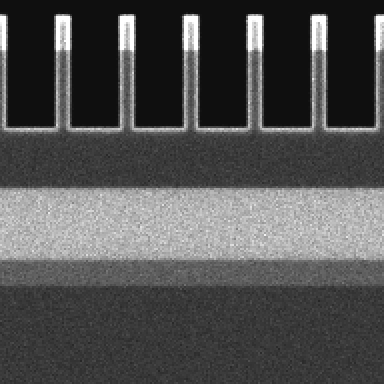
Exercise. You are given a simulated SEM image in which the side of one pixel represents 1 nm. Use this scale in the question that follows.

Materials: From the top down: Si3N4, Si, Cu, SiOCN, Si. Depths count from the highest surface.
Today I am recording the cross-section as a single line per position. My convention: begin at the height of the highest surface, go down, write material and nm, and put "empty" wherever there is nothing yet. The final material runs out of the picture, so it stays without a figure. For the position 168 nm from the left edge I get empty 112, Si 60, Cu 72, SiOCN 26, Si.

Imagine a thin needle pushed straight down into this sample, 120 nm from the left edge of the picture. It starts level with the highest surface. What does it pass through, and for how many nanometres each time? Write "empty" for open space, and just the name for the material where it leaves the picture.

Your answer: Si3N4 34, Si 138, Cu 72, SiOCN 26, Si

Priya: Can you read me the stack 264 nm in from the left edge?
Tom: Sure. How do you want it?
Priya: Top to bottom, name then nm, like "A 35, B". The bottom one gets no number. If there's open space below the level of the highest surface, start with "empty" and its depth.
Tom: empty 112, Si 60, Cu 72, SiOCN 26, Si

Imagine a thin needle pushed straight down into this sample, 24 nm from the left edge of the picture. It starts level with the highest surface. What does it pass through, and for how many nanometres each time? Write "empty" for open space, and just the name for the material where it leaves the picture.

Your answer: empty 112, Si 60, Cu 72, SiOCN 26, Si